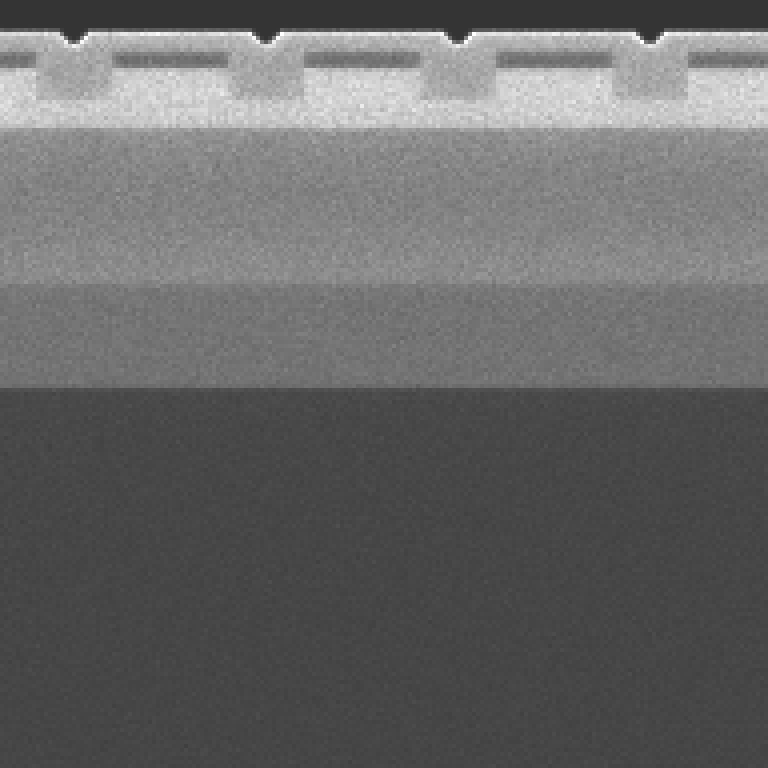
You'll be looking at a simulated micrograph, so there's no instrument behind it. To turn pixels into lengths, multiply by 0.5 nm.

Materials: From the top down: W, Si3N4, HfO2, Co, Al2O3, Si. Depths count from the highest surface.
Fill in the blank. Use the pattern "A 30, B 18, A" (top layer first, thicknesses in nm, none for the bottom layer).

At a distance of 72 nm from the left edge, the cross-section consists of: W 10, Si3N4 8, HfO2 30, Co 78, Al2O3 52, Si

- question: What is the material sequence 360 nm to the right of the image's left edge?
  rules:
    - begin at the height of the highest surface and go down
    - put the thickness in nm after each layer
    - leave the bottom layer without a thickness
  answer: W 10, Si3N4 8, HfO2 30, Co 78, Al2O3 52, Si